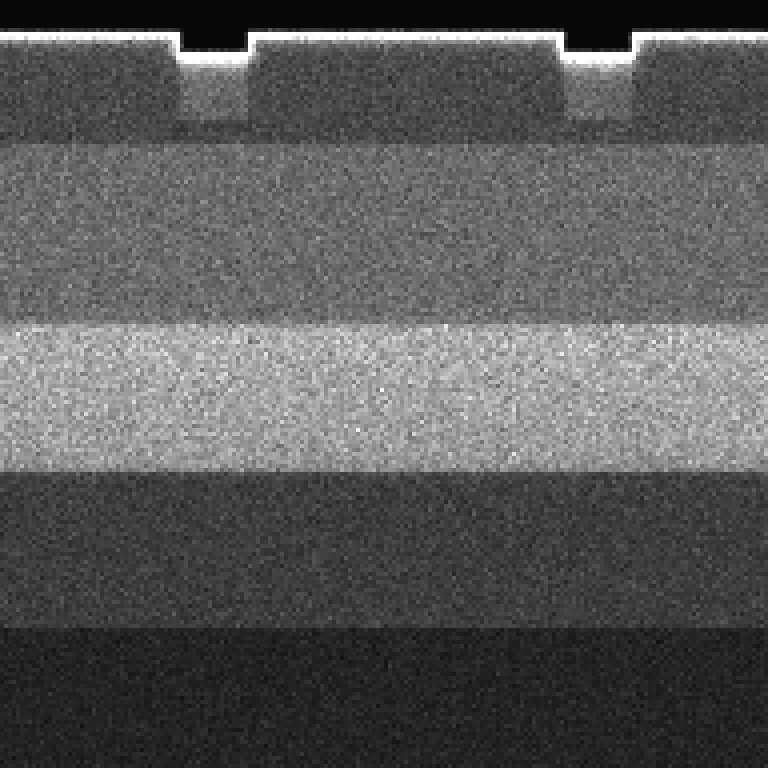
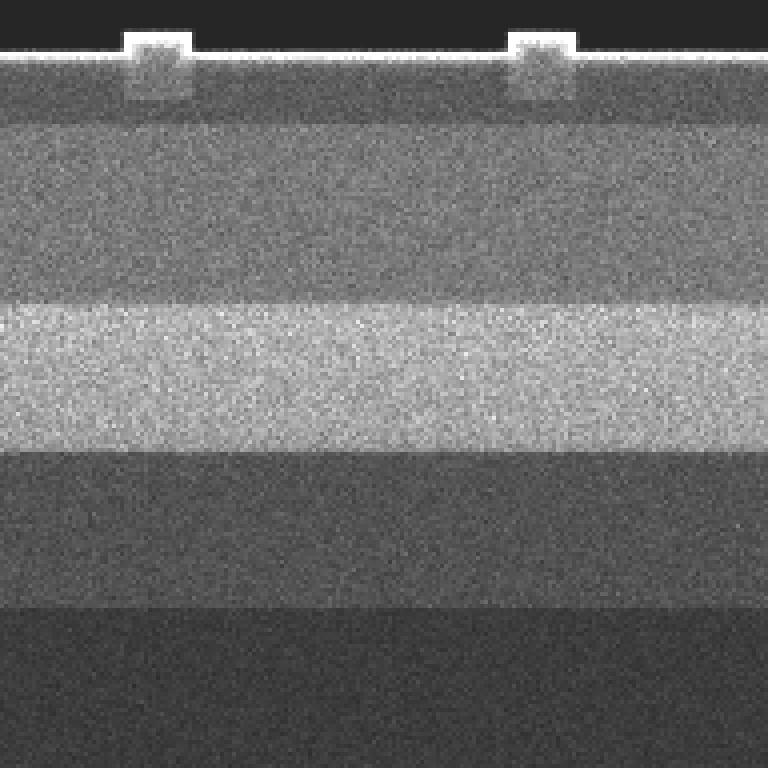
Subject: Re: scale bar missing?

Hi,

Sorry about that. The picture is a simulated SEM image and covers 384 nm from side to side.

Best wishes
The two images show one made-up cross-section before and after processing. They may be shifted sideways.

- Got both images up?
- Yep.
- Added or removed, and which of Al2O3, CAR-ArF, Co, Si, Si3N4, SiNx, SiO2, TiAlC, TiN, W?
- removed, Si3N4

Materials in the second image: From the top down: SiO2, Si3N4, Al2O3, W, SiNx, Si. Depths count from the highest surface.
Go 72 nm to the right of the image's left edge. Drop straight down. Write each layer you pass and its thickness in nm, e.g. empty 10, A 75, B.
SiO2 34, Si3N4 12, Al2O3 90, W 74, SiNx 78, Si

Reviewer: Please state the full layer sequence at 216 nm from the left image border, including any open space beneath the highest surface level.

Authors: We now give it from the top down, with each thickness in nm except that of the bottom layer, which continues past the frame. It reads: empty 10, Si3N4 36, Al2O3 90, W 74, SiNx 78, Si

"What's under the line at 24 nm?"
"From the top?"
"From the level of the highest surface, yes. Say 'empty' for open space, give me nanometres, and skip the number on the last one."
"empty 10, Si3N4 36, Al2O3 90, W 74, SiNx 78, Si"